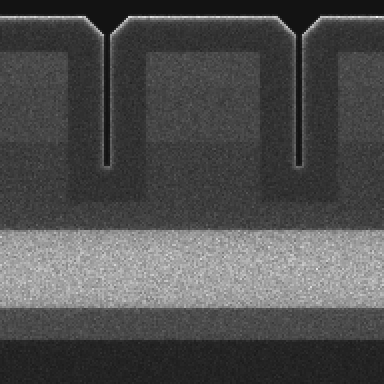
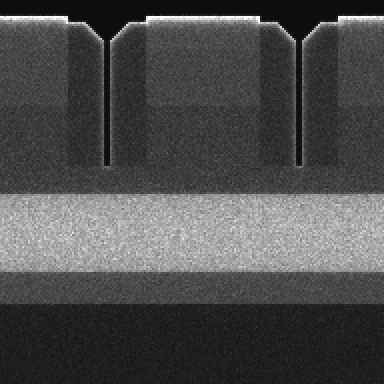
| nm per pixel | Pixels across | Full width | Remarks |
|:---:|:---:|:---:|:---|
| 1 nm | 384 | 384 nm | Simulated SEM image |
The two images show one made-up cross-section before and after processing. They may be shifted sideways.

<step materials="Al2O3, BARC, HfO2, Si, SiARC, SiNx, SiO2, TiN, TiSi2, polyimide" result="removed SiNx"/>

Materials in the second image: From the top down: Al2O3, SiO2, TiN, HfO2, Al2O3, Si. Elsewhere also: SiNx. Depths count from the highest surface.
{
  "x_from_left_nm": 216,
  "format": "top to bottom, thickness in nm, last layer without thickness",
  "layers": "Al2O3 34, SiO2 56, TiN 88, HfO2 78, Al2O3 32, Si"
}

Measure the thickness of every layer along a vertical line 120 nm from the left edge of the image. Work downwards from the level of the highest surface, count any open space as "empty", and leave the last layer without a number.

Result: empty 14, SiNx 136, TiN 28, HfO2 78, Al2O3 32, Si